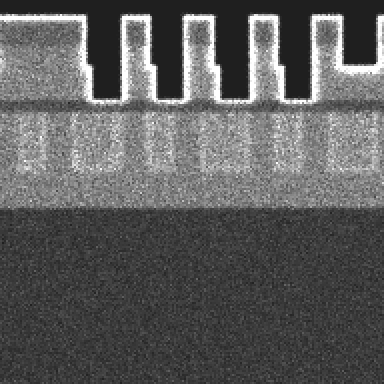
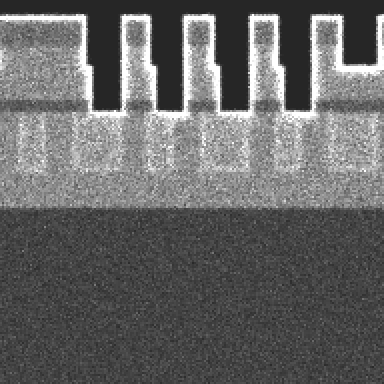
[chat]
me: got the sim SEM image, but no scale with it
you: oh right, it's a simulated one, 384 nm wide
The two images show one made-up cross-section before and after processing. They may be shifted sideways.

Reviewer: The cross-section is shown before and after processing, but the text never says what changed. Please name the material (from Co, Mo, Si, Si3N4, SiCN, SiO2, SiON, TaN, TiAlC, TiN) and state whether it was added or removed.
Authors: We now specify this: SiCN, removed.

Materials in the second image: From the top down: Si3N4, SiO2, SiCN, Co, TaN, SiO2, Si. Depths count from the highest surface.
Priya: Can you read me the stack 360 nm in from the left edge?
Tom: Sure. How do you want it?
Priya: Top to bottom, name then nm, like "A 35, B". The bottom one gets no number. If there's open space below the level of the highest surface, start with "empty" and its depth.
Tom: empty 50, SiO2 34, SiCN 12, Co 54, TaN 6, SiO2 36, Si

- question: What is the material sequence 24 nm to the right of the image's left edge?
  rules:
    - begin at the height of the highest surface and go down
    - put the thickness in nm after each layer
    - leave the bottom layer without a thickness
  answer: Si3N4 30, SiO2 54, SiCN 12, Co 54, TaN 6, SiO2 36, Si